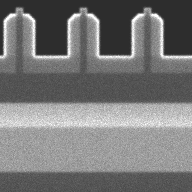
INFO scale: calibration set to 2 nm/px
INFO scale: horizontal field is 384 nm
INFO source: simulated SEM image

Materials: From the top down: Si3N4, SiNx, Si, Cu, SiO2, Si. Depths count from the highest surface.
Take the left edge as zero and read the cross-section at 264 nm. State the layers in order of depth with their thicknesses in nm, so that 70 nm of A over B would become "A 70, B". empty 24, Si3N4 72, SiNx 34, Si 60, Cu 48, SiO2 90, Si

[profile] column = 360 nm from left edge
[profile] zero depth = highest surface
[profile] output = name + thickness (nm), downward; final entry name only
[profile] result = empty 96, SiNx 34, Si 60, Cu 48, SiO2 90, Si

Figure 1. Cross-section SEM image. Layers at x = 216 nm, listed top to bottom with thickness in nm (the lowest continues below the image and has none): empty 96, SiNx 34, Si 60, Cu 48, SiO2 90, Si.